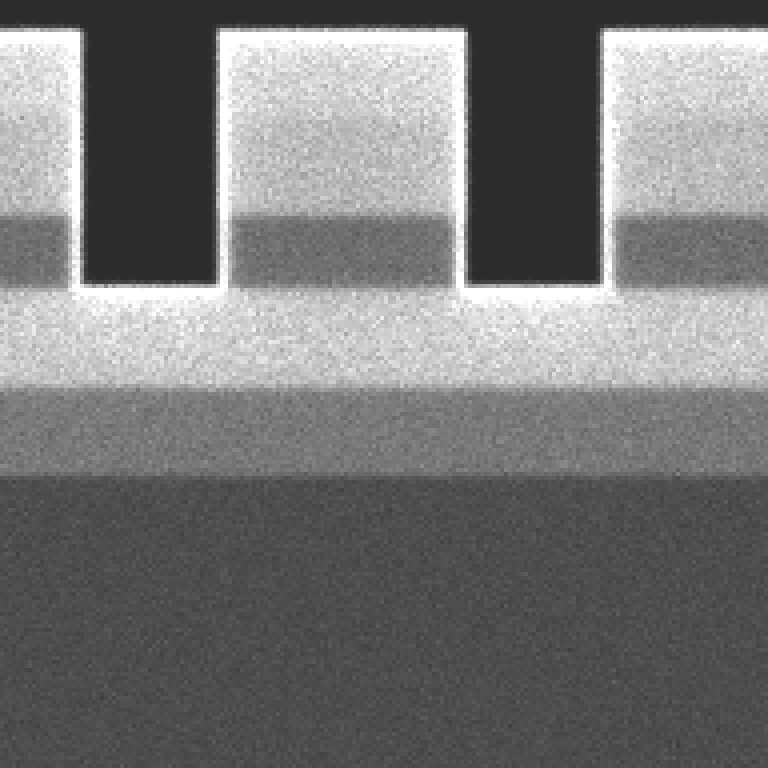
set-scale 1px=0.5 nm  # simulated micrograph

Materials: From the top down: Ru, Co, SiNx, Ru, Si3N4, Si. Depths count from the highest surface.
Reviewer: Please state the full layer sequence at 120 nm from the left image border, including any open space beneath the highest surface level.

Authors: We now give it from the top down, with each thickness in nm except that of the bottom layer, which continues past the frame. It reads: Ru 42, Co 50, SiNx 36, Ru 50, Si3N4 44, Si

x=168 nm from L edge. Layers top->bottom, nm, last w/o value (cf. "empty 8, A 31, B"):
Ru 42, Co 50, SiNx 36, Ru 50, Si3N4 44, Si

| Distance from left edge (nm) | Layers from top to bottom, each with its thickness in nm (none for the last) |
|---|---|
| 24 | Ru 42, Co 50, SiNx 36, Ru 50, Si3N4 44, Si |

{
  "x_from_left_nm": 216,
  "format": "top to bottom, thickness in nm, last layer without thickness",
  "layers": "Ru 42, Co 50, SiNx 36, Ru 50, Si3N4 44, Si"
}